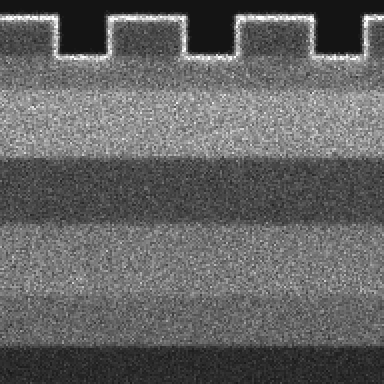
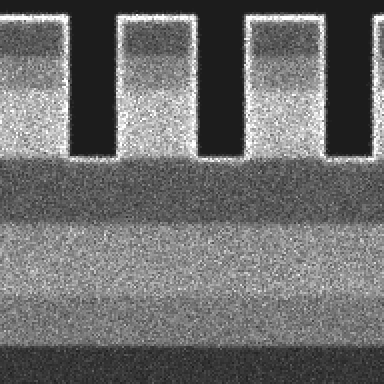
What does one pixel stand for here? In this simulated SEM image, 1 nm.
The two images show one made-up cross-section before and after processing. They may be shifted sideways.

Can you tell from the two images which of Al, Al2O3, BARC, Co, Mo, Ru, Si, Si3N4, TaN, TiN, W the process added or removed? Yes, it removed Co and W.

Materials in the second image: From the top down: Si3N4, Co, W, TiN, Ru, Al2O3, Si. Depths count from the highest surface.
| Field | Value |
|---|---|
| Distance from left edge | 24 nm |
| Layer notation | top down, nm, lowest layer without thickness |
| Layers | Si3N4 40, Co 34, W 68, TiN 66, Ru 72, Al2O3 50, Si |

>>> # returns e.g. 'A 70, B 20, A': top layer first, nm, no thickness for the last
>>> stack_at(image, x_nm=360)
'empty 142, TiN 66, Ru 72, Al2O3 50, Si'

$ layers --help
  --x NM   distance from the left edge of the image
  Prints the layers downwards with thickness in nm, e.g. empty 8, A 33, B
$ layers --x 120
Si3N4 40, Co 34, W 68, TiN 66, Ru 72, Al2O3 50, Si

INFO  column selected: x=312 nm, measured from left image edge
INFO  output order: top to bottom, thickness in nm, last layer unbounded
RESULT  Si3N4 40, Co 34, W 68, TiN 66, Ru 72, Al2O3 50, Si